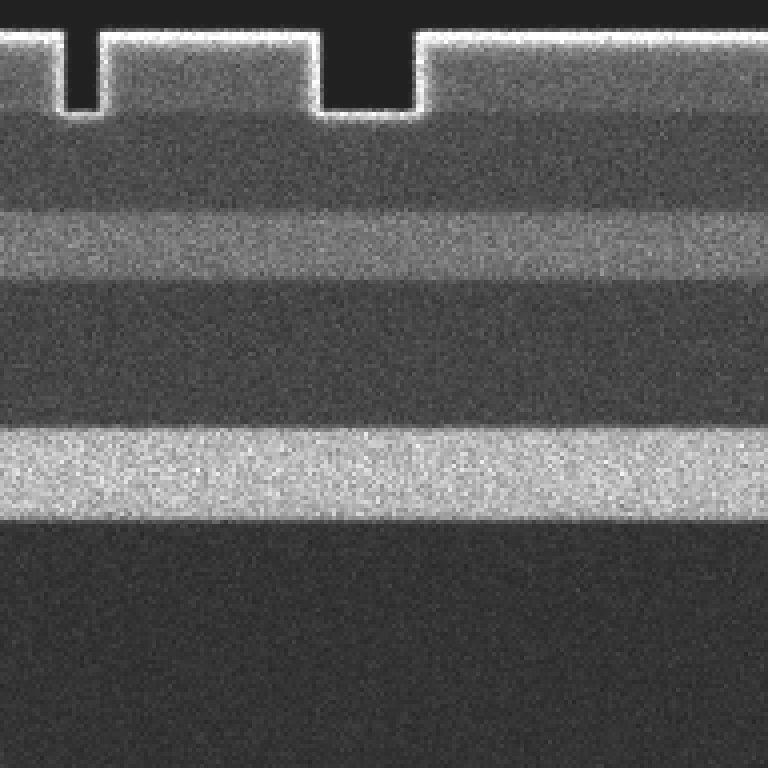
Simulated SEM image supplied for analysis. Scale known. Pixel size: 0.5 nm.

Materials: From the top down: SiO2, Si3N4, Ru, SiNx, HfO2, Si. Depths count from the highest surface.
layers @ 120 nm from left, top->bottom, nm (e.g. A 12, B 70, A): SiO2 40, Si3N4 50, Ru 34, SiNx 74, HfO2 46, Si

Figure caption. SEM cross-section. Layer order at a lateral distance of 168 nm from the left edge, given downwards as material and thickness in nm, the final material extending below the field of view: empty 40, Si3N4 50, Ru 34, SiNx 74, HfO2 46, Si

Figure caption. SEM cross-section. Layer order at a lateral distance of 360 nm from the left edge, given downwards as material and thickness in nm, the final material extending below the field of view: SiO2 40, Si3N4 50, Ru 34, SiNx 74, HfO2 46, Si